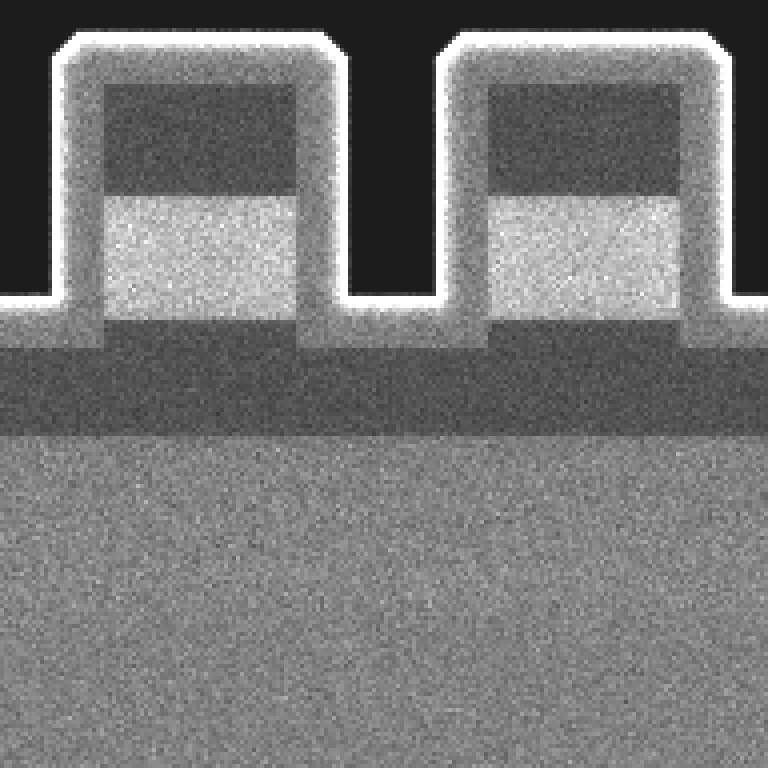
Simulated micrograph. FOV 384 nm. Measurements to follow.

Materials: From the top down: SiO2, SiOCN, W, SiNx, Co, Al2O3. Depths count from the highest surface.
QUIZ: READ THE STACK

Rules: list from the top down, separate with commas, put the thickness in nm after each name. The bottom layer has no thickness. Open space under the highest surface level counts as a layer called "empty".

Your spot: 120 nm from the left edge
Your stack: SiO2 26, SiOCN 56, W 62, SiNx 58, Co 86, Al2O3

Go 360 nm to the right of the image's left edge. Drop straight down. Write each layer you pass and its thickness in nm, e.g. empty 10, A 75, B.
empty 8, SiO2 150, SiNx 44, Co 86, Al2O3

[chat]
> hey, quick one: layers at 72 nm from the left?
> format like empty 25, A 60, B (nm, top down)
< SiO2 26, SiOCN 56, W 62, SiNx 58, Co 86, Al2O3